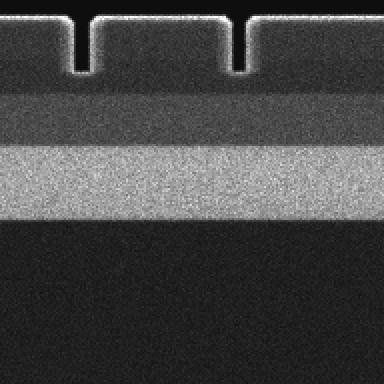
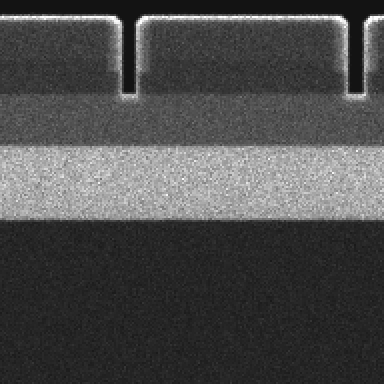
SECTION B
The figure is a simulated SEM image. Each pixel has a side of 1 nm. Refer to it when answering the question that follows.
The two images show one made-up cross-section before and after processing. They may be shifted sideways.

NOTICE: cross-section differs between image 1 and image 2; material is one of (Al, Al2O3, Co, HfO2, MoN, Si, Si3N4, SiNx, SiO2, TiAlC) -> removed: SiNx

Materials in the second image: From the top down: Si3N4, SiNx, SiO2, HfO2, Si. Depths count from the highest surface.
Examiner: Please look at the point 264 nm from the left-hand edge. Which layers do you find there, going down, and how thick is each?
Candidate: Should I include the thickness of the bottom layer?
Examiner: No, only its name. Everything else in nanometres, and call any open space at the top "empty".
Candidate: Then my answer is Si3N4 44, SiNx 34, SiO2 52, HfO2 74, Si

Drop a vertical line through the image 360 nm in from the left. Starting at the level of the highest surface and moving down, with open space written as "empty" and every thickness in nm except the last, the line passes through empty 78, SiO2 52, HfO2 74, Si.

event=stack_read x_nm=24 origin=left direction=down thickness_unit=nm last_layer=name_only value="Si3N4 44, SiNx 34, SiO2 52, HfO2 74, Si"